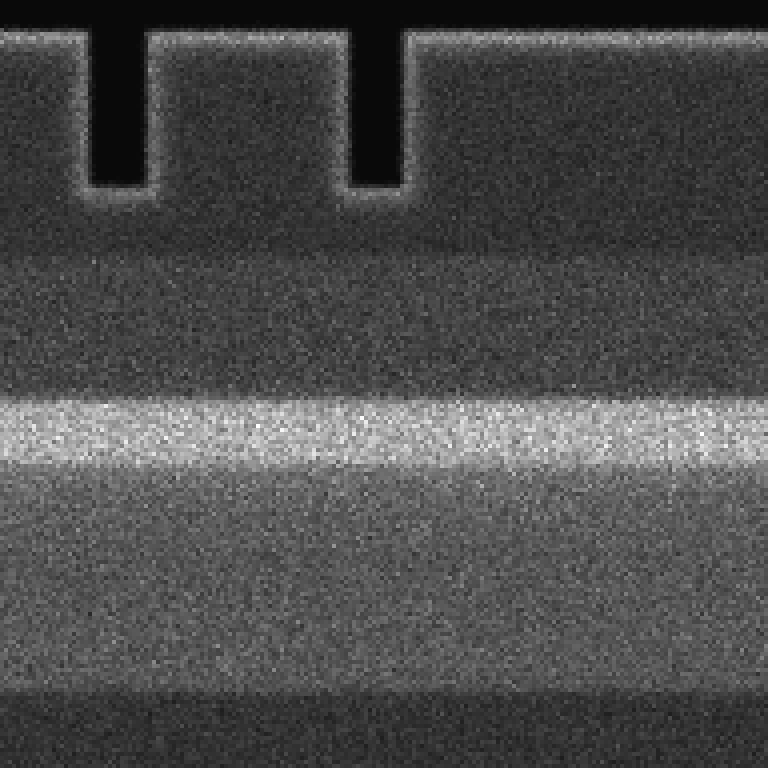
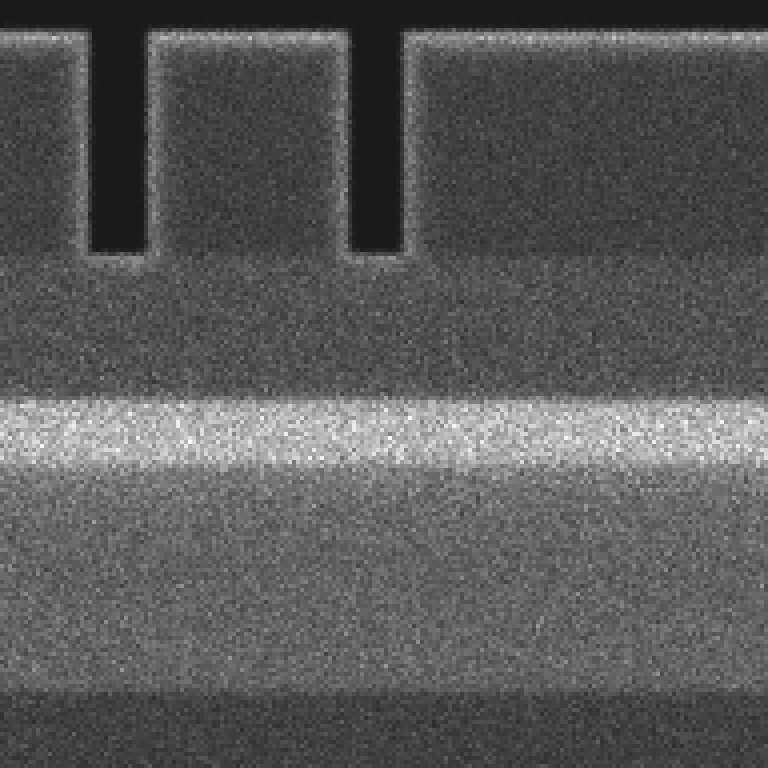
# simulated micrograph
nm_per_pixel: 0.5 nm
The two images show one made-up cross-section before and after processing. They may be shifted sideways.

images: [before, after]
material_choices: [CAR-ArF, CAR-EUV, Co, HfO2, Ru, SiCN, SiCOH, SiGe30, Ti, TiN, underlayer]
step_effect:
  removed: underlayer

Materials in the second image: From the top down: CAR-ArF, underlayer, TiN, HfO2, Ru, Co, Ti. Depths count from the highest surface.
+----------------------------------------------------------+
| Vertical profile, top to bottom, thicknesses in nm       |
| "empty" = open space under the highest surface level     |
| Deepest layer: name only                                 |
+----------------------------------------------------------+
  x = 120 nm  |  CAR-ArF 78, underlayer 34, TiN 72, HfO2 32, Ru 42, Co 72, Ti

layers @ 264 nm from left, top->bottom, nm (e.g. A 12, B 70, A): CAR-ArF 78, underlayer 34, TiN 72, HfO2 32, Ru 42, Co 72, Ti